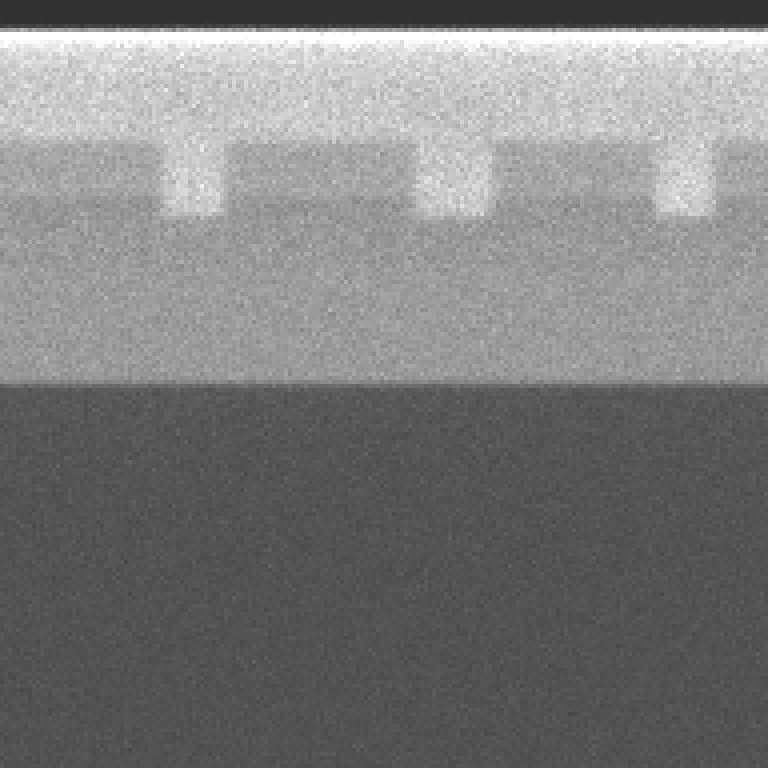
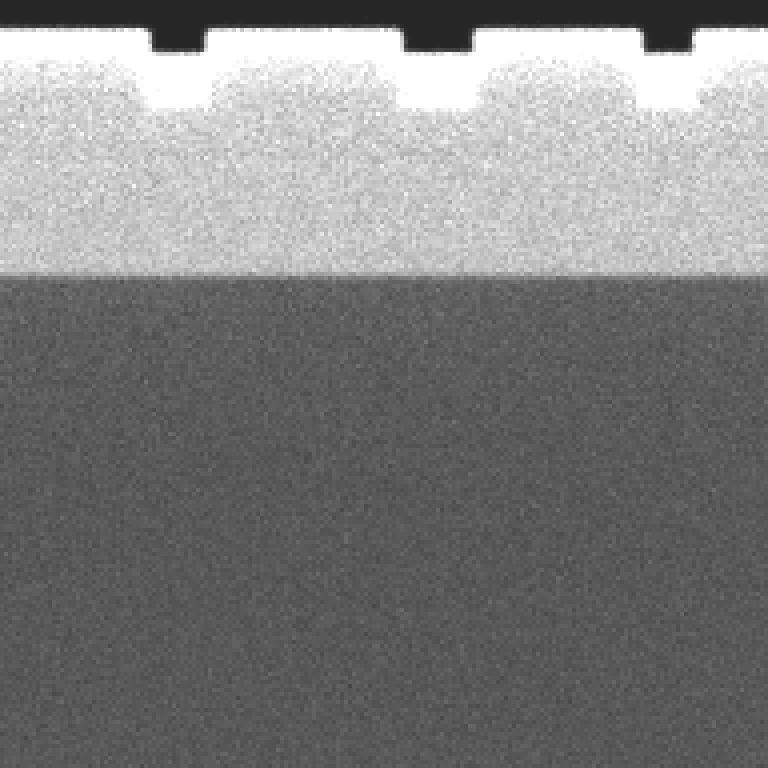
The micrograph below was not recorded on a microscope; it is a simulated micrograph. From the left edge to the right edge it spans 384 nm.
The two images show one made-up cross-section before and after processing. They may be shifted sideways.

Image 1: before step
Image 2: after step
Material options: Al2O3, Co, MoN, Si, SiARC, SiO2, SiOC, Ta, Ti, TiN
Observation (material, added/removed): Co, removed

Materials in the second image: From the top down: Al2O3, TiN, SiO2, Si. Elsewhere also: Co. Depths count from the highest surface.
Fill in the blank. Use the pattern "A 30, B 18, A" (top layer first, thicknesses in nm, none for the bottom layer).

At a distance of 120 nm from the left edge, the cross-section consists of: Al2O3 28, TiN 36, SiO2 58, Si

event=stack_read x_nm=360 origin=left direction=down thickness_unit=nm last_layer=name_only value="Al2O3 28, TiN 36, SiO2 58, Si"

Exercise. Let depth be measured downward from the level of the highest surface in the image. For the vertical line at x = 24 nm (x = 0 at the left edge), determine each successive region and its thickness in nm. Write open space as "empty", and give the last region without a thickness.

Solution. Al2O3 28, TiN 36, SiO2 58, Si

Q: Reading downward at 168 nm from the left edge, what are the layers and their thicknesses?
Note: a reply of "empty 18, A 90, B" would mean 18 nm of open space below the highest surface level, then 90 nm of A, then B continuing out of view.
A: Al2O3 28, TiN 36, SiO2 58, Si